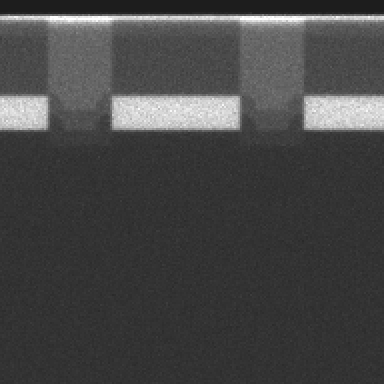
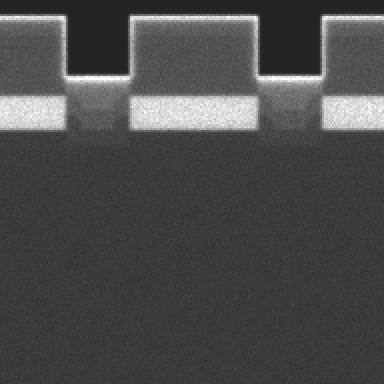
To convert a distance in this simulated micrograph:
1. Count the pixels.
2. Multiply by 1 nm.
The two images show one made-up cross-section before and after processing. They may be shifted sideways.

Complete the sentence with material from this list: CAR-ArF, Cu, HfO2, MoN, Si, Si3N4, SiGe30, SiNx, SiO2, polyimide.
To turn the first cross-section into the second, SiO2 must be removed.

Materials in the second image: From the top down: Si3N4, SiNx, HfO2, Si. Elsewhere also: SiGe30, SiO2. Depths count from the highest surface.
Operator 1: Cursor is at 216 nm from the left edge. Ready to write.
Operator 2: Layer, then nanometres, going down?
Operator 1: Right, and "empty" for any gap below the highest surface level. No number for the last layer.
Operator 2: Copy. Si3N4 20, SiNx 60, HfO2 34, Si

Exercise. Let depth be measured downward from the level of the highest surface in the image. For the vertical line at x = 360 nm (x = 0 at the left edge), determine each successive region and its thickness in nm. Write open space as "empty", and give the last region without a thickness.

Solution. Si3N4 20, SiNx 60, HfO2 34, Si